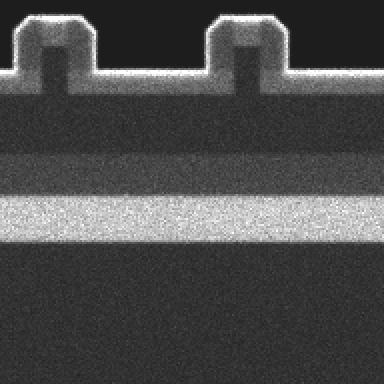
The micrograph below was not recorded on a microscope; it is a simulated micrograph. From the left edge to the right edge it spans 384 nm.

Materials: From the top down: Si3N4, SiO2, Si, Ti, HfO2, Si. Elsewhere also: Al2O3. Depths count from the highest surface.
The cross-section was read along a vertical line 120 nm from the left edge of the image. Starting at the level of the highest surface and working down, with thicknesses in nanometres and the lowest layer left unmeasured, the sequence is empty 54, SiO2 24, Si 60, Ti 42, HfO2 46, Si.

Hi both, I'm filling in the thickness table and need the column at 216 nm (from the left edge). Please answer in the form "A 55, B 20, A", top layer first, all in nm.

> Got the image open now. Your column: empty 4, Si3N4 50, SiO2 24, Si 60, Ti 42, HfO2 46, Si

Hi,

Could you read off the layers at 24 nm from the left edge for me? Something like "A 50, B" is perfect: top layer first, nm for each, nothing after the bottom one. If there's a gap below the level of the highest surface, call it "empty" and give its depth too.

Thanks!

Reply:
empty 4, Si3N4 50, SiO2 24, Si 60, Ti 42, HfO2 46, Si